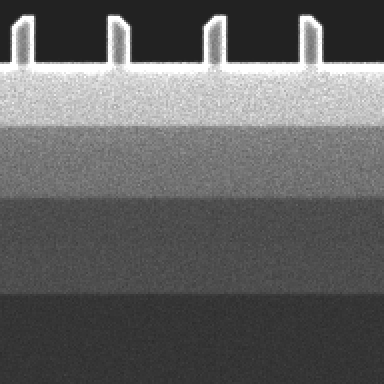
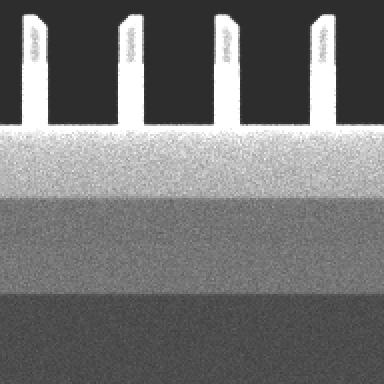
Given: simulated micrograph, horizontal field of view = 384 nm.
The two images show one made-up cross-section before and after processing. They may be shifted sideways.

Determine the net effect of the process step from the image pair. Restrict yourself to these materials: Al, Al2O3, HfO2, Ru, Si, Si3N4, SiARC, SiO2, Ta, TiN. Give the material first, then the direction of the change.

HfO2: removed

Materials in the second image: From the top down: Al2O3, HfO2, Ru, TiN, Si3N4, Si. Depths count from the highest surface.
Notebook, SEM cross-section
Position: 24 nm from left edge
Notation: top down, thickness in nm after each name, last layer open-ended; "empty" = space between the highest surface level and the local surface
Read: Al2O3 48, HfO2 62, Ru 72, TiN 46, Si3N4 50, Si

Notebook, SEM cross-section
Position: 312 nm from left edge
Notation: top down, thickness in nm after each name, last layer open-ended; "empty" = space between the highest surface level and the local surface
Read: empty 10, Al2O3 38, HfO2 62, Ru 72, TiN 46, Si3N4 50, Si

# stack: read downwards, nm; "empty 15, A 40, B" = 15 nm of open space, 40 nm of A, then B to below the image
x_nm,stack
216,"Al2O3 48, HfO2 62, Ru 72, TiN 46, Si3N4 50, Si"